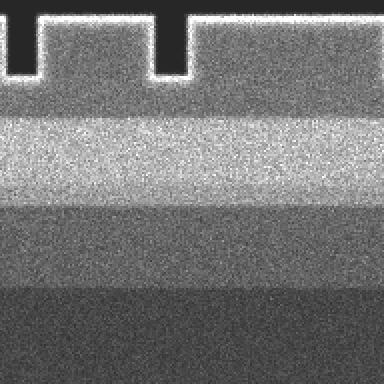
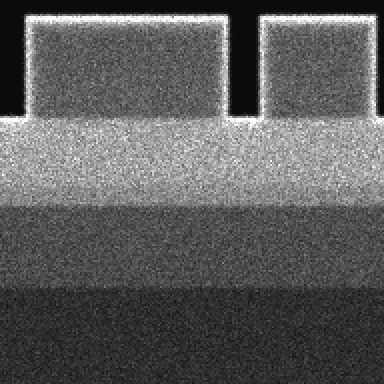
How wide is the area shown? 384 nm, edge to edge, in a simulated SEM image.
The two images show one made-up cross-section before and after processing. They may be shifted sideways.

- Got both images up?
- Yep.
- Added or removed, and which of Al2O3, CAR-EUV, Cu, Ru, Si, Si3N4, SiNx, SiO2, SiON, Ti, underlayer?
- removed, underlayer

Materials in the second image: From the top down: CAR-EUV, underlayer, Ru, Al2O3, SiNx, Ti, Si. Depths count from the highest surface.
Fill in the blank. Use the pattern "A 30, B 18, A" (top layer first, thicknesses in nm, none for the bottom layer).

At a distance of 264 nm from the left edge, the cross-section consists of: CAR-EUV 60, underlayer 42, Ru 68, Al2O3 20, SiNx 28, Ti 54, Si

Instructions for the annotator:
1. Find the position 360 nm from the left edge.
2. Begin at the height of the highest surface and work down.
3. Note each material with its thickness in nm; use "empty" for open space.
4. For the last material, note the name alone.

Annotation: CAR-EUV 60, underlayer 42, Ru 68, Al2O3 20, SiNx 28, Ti 54, Si